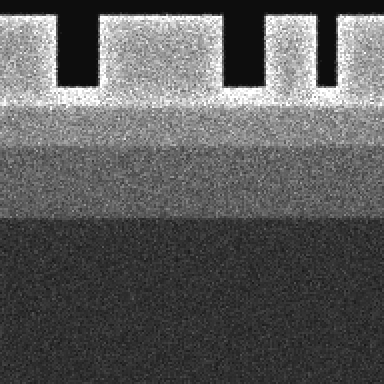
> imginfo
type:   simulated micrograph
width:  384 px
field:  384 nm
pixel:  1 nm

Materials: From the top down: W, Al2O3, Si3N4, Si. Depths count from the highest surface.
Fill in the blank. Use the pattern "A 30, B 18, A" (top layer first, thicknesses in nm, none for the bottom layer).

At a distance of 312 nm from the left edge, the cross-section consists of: W 90, Al2O3 40, Si3N4 72, Si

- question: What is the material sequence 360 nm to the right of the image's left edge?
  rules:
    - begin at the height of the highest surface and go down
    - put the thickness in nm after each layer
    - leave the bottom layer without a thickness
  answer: W 90, Al2O3 40, Si3N4 72, Si